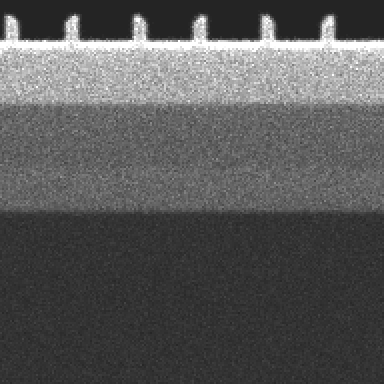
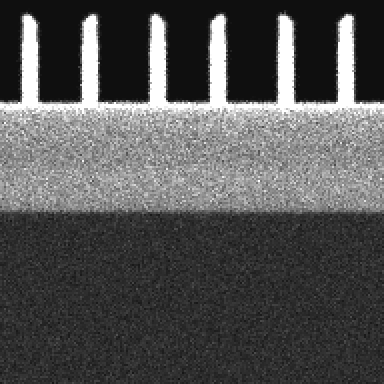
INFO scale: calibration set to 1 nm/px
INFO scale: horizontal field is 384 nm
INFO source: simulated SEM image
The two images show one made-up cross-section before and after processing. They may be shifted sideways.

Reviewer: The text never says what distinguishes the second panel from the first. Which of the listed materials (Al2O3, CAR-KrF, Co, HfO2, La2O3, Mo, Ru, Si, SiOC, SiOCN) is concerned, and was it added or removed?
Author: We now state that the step removed HfO2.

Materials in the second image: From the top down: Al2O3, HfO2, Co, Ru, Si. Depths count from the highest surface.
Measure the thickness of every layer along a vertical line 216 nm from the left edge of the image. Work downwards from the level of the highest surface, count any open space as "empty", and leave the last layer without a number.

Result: empty 2, Al2O3 24, HfO2 62, Co 64, Ru 44, Si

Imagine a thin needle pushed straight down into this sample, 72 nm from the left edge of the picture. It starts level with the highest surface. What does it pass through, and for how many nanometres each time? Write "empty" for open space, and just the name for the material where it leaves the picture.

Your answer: empty 88, Co 64, Ru 44, Si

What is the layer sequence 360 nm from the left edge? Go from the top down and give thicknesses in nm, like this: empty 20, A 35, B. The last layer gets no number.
empty 88, Co 64, Ru 44, Si